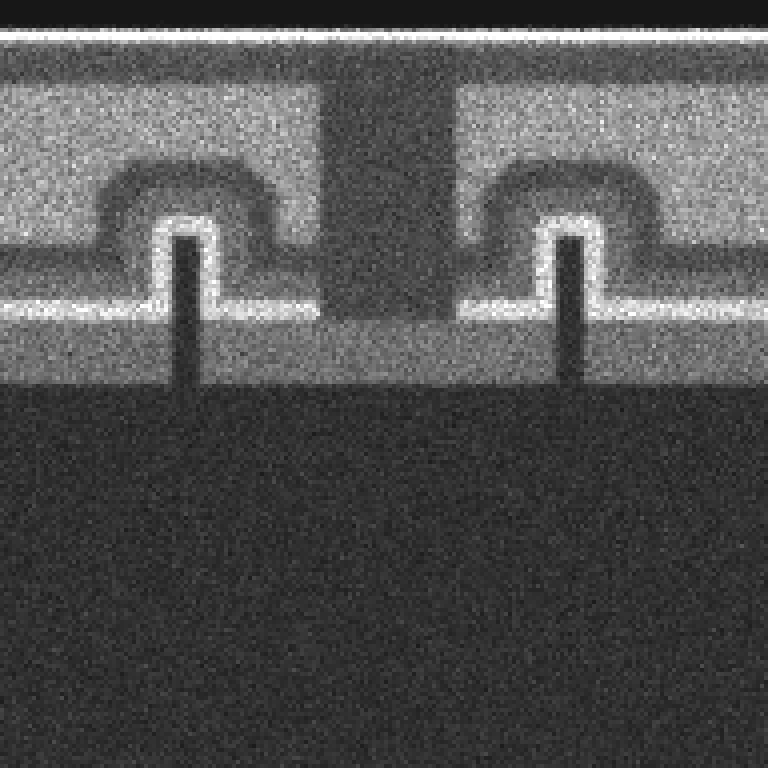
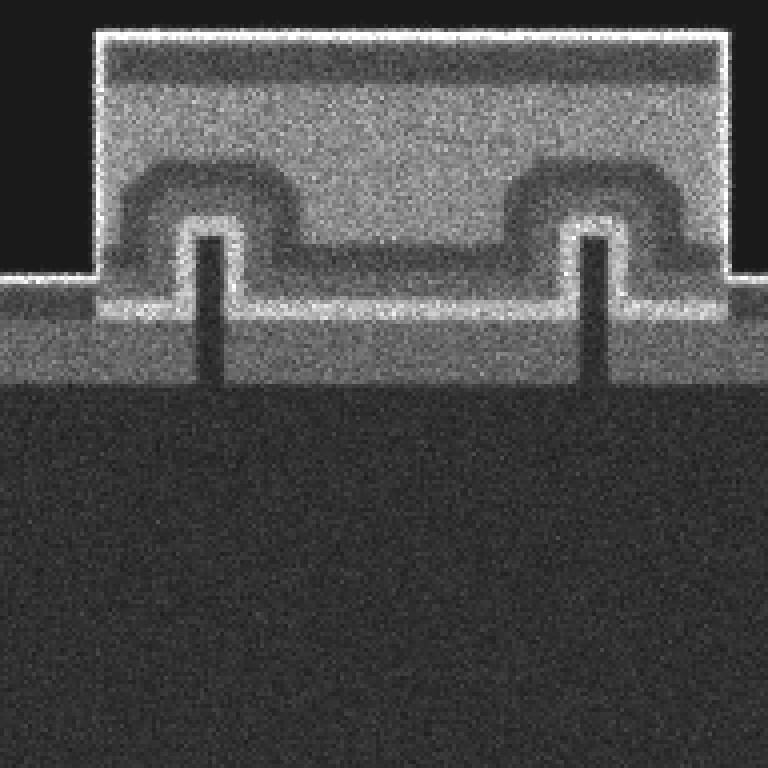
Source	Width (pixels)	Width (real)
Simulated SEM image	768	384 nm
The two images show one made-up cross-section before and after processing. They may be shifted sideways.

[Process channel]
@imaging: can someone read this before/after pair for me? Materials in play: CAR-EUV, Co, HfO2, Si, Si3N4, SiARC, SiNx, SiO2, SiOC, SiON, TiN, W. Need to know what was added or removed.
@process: SiNx removed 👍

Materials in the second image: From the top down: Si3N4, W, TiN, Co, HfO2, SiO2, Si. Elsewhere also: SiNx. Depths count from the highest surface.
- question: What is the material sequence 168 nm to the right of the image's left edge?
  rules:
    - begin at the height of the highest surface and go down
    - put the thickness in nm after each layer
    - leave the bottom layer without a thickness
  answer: Si3N4 26, W 80, TiN 14, Co 14, HfO2 10, SiO2 32, Si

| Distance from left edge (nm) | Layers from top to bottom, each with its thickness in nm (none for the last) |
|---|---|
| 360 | Si3N4 26, W 80, TiN 14, Co 14, HfO2 10, SiO2 32, Si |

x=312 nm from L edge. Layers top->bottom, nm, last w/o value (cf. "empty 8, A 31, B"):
Si3N4 26, W 38, TiN 14, Co 18, HfO2 48, SiO2 32, Si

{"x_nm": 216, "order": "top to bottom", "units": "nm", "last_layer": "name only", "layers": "Si3N4 26, W 80, TiN 14, Co 14, HfO2 10, SiO2 32, Si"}